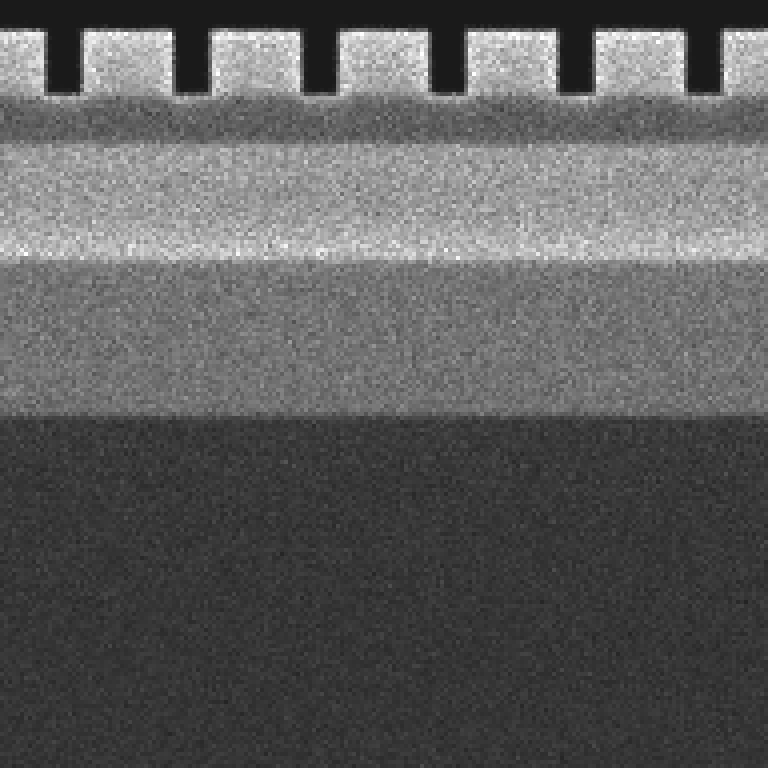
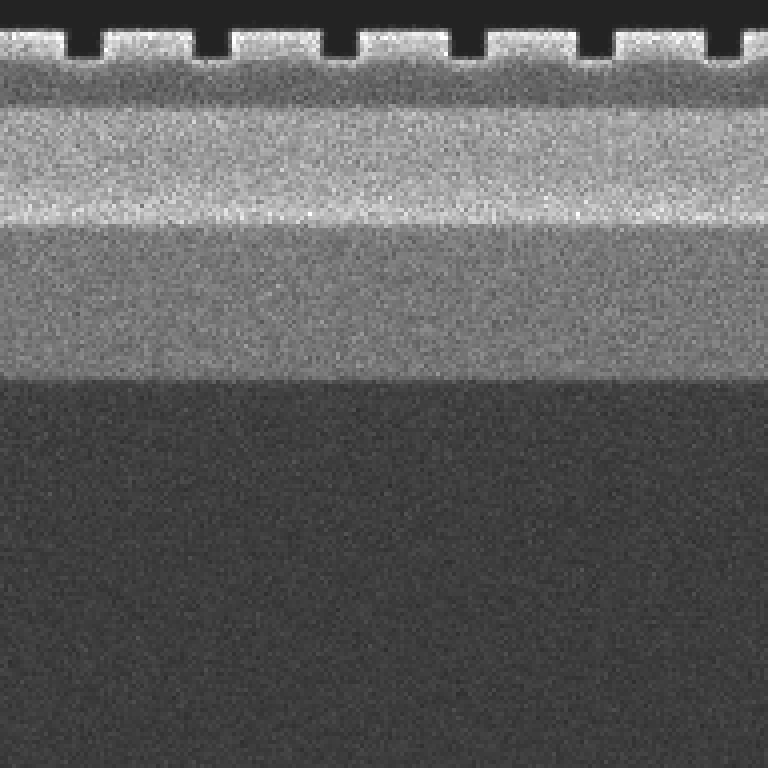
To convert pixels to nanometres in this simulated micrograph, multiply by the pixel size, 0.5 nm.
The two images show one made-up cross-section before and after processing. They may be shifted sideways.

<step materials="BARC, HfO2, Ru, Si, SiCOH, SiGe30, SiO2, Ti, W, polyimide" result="removed Ru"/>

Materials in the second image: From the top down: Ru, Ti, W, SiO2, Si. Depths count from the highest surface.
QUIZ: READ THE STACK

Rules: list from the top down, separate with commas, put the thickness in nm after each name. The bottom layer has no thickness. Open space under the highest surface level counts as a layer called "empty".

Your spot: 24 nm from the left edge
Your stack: Ru 14, Ti 24, W 58, SiO2 78, Si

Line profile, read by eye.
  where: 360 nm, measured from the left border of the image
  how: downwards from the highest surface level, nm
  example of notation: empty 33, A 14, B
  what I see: empty 14, Ti 24, W 58, SiO2 78, Si